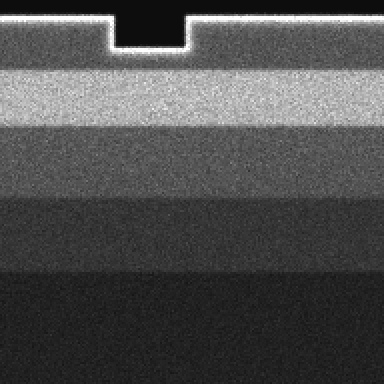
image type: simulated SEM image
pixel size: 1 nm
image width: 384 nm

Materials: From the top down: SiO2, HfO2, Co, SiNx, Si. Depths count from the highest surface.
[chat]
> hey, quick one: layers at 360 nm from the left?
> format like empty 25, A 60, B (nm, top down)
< SiO2 54, HfO2 56, Co 72, SiNx 74, Si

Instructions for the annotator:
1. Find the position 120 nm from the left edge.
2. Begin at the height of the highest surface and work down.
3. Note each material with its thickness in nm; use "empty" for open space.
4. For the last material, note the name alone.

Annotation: empty 32, SiO2 22, HfO2 56, Co 72, SiNx 74, Si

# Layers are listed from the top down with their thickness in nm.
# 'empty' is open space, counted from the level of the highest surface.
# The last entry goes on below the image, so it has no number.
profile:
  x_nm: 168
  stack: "empty 32, SiO2 22, HfO2 56, Co 72, SiNx 74, Si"